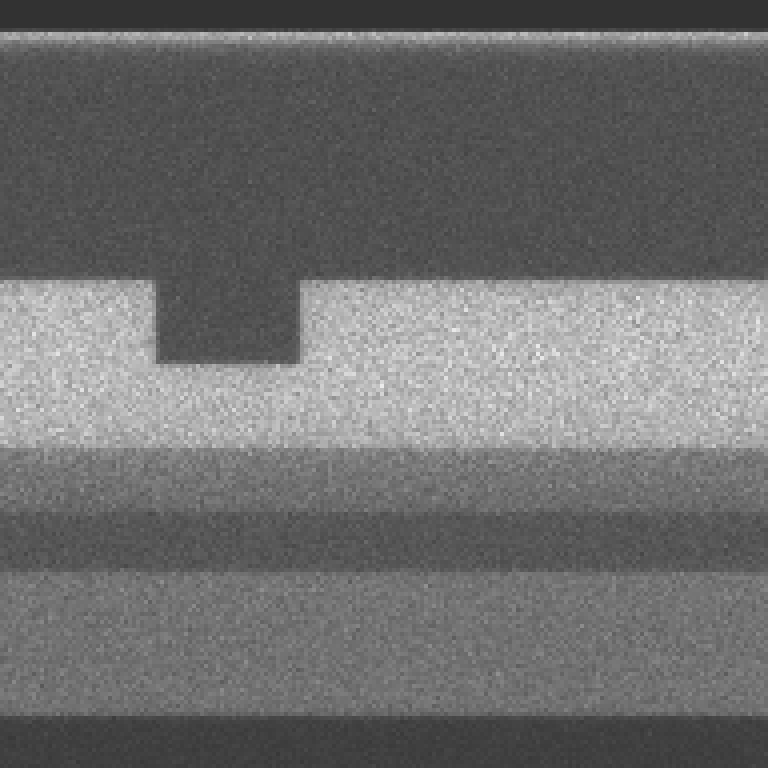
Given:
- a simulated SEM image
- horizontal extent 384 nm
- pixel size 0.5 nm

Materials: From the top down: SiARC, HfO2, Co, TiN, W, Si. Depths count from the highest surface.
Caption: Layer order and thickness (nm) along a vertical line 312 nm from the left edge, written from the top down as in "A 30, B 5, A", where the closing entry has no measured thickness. SiARC 124, HfO2 84, Co 32, TiN 30, W 72, Si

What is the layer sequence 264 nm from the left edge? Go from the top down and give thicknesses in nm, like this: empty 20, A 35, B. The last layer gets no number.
SiARC 124, HfO2 84, Co 32, TiN 30, W 72, Si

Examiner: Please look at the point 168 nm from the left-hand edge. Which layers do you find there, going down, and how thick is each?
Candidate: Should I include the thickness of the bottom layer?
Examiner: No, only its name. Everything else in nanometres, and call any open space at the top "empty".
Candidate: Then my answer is SiARC 124, HfO2 84, Co 32, TiN 30, W 72, Si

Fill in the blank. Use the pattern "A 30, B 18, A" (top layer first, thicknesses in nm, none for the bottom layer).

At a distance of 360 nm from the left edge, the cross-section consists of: SiARC 124, HfO2 84, Co 32, TiN 30, W 72, Si